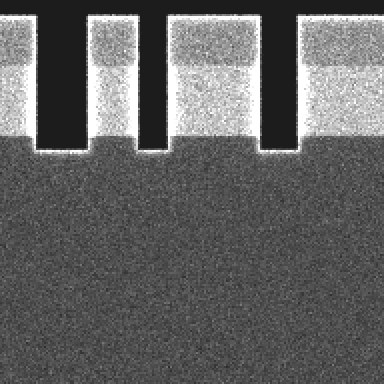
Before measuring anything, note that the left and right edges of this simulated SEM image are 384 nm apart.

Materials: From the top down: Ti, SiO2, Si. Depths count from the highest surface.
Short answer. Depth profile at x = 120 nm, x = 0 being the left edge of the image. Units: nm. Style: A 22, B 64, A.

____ Ti 50, SiO2 70, Si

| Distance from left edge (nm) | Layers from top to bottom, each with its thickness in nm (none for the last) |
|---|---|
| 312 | Ti 50, SiO2 70, Si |